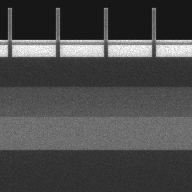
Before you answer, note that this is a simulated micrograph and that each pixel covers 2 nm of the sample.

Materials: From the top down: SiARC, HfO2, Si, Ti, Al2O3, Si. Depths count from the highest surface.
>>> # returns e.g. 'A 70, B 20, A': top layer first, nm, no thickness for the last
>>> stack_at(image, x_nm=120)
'empty 64, SiARC 10, HfO2 24, Si 60, Ti 60, Al2O3 66, Si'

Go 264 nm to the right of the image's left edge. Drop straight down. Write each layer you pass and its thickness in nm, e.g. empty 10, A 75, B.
empty 64, SiARC 10, HfO2 24, Si 60, Ti 60, Al2O3 66, Si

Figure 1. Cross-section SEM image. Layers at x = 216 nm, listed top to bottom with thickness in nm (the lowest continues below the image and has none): empty 64, SiARC 10, HfO2 24, Si 60, Ti 60, Al2O3 66, Si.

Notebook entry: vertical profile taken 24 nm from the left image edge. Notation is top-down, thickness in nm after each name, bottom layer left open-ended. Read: empty 64, SiARC 10, HfO2 24, Si 60, Ti 60, Al2O3 66, Si